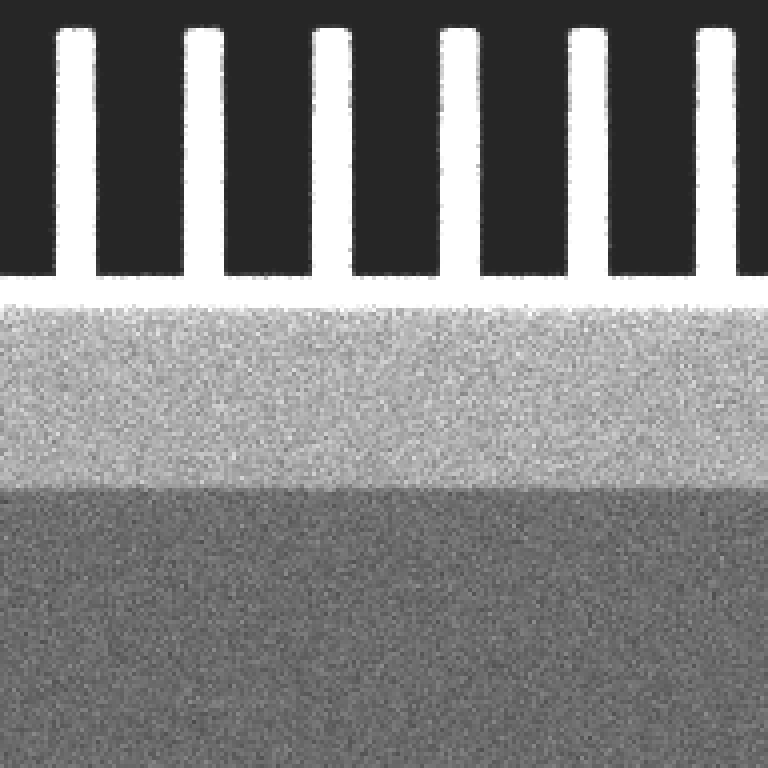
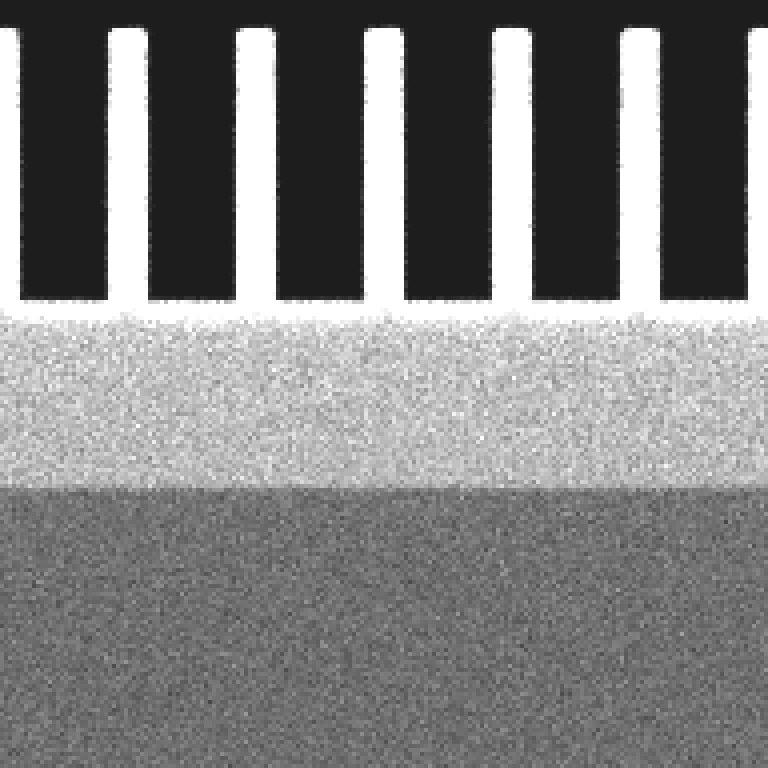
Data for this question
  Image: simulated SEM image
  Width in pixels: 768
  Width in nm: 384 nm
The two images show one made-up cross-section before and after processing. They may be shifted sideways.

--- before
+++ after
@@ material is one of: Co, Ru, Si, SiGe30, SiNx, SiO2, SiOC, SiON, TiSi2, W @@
Ru removed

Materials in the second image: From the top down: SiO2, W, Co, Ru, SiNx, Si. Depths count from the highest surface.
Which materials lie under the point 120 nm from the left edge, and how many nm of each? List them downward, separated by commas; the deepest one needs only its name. SiO2 40, W 70, Co 14, Ru 12, SiNx 92, Si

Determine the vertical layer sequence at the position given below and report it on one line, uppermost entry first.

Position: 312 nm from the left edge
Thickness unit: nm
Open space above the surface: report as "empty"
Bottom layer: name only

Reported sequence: SiO2 40, W 70, Co 14, Ru 12, SiNx 92, Si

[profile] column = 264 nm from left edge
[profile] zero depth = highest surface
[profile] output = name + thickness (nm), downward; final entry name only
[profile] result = empty 136, SiNx 92, Si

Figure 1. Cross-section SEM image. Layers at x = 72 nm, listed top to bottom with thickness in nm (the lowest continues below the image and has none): empty 136, SiNx 92, Si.